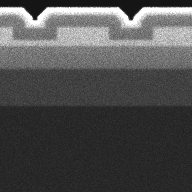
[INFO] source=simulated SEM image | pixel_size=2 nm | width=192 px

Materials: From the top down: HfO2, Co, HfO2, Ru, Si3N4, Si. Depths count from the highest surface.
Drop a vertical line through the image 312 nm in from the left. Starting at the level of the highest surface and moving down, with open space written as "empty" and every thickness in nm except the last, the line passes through HfO2 14, Co 24, HfO2 38, Ru 46, Si3N4 74, Si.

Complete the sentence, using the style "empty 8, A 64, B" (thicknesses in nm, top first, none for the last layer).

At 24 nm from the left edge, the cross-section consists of HfO2 14, Co 24, HfO2 38, Ru 46, Si3N4 74, Si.